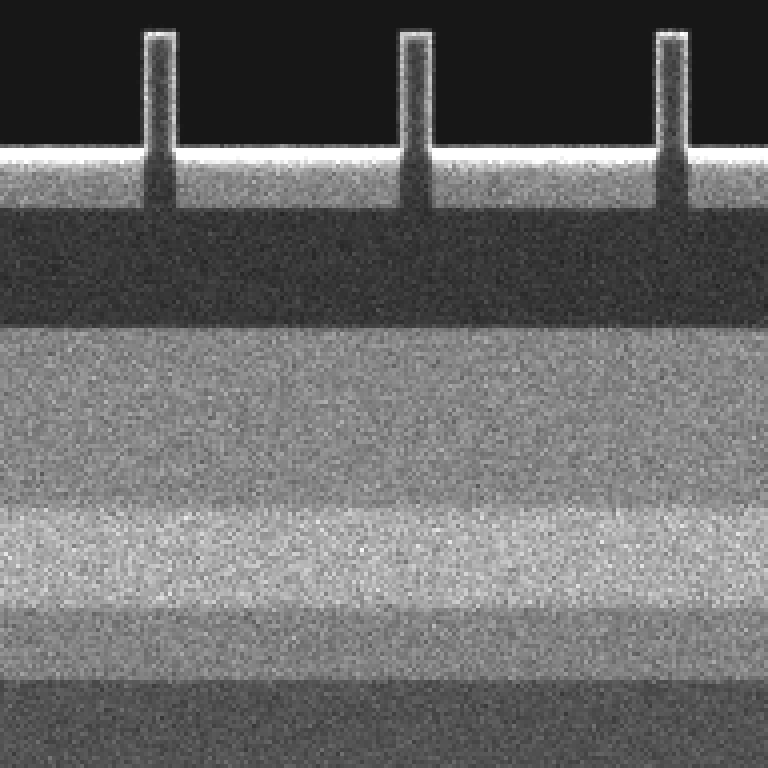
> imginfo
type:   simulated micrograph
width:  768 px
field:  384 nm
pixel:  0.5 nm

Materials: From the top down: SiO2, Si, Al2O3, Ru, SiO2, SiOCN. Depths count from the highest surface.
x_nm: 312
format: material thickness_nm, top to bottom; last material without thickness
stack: empty 58, SiO2 30, Si 60, Al2O3 90, Ru 50, SiO2 36, SiOCN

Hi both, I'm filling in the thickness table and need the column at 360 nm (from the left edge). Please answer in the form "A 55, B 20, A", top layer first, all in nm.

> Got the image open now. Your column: empty 58, SiO2 30, Si 60, Al2O3 90, Ru 50, SiO2 36, SiOCN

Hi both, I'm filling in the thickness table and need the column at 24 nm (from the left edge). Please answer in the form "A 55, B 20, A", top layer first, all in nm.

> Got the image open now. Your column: empty 58, SiO2 30, Si 60, Al2O3 90, Ru 50, SiO2 36, SiOCN